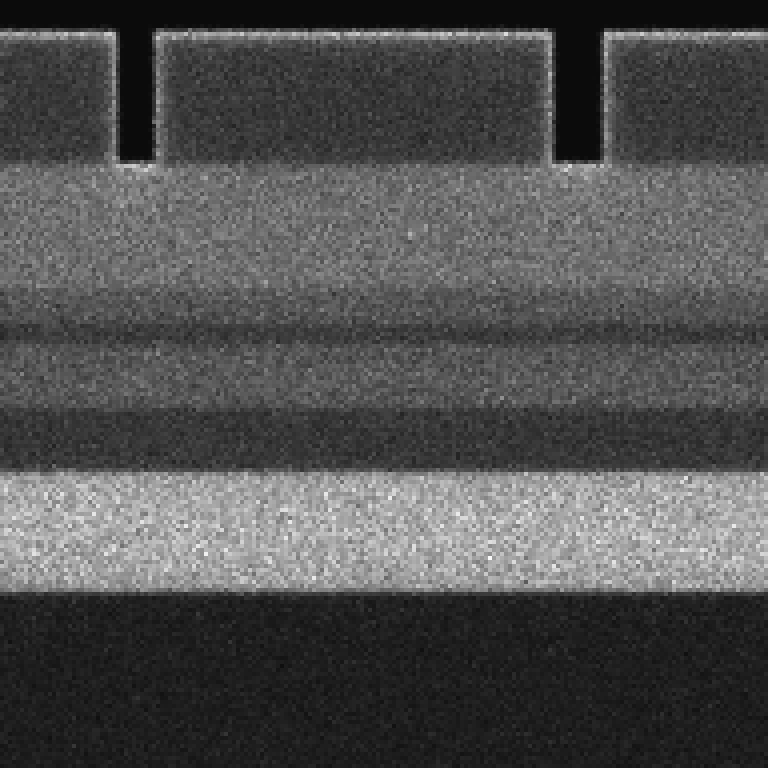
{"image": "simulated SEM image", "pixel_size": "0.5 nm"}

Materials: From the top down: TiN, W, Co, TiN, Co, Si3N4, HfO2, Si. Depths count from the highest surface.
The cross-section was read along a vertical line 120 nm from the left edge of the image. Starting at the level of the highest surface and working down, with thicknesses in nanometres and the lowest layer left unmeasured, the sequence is TiN 66, W 62, Co 18, TiN 10, Co 32, Si3N4 32, HfO2 60, Si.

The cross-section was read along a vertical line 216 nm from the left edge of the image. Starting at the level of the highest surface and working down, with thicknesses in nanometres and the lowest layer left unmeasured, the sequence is TiN 66, W 62, Co 18, TiN 10, Co 32, Si3N4 32, HfO2 60, Si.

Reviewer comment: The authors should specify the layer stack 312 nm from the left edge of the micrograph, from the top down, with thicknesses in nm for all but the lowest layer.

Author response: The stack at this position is TiN 66, W 62, Co 18, TiN 10, Co 32, Si3N4 32, HfO2 60, Si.